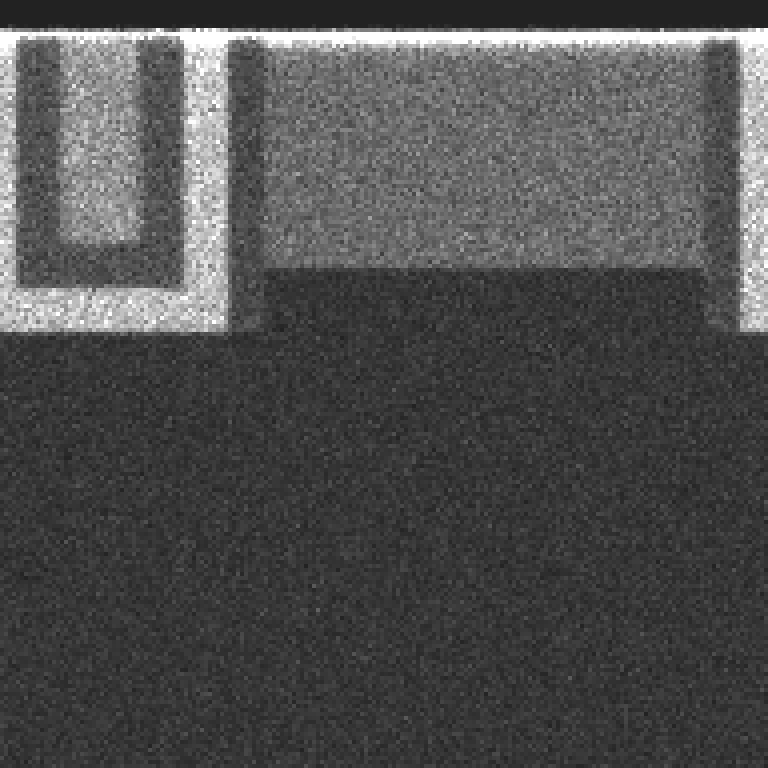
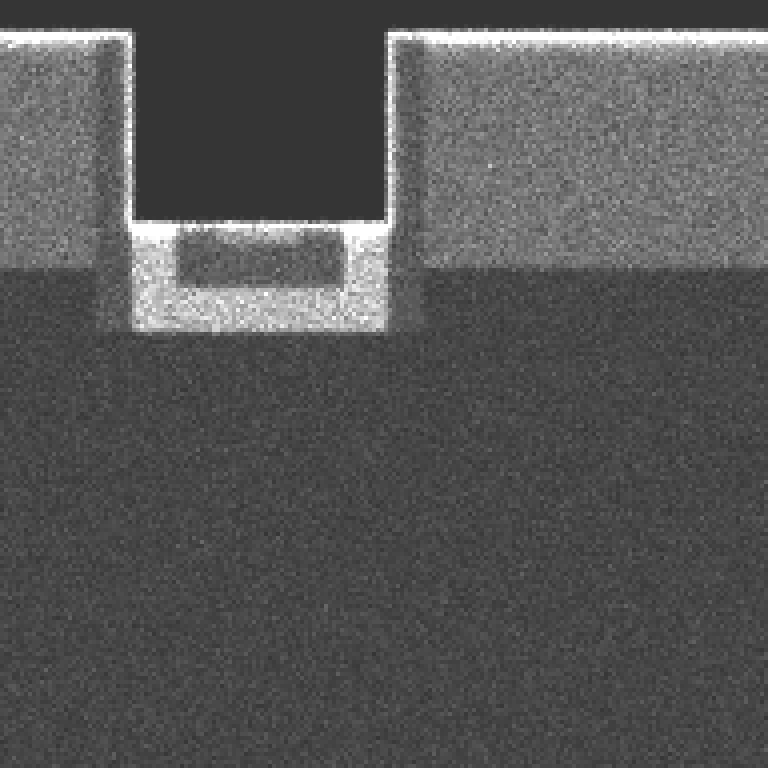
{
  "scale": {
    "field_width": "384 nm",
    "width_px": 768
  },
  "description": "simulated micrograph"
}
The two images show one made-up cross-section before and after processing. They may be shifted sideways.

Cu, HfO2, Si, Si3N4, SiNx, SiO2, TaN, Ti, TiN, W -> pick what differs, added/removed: HfO2 and TiN and W removed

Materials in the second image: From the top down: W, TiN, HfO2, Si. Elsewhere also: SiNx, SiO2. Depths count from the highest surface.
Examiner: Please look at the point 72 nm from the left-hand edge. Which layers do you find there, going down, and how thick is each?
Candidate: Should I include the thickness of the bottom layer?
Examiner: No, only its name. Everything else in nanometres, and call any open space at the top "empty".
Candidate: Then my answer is empty 96, HfO2 54, Si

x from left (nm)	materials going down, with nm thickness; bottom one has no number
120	empty 96, W 10, TiN 22, HfO2 22, Si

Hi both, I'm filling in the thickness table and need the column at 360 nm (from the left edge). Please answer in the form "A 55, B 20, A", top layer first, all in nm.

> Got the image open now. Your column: SiO2 118, Si